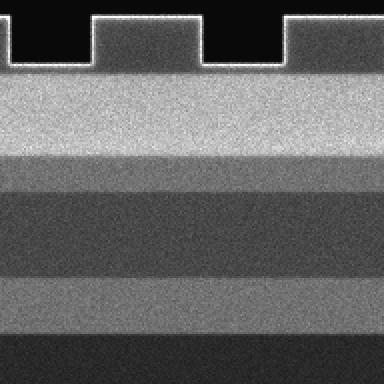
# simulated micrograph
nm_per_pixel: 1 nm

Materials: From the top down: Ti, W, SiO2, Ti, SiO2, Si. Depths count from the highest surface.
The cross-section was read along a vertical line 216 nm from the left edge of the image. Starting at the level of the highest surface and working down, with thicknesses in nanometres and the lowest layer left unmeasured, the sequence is empty 48, Ti 10, W 82, SiO2 36, Ti 86, SiO2 56, Si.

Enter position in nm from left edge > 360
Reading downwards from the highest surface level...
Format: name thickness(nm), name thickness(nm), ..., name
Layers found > Ti 58, W 82, SiO2 36, Ti 86, SiO2 56, Si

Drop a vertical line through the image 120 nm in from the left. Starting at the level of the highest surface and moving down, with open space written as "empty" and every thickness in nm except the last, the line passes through Ti 58, W 82, SiO2 36, Ti 86, SiO2 56, Si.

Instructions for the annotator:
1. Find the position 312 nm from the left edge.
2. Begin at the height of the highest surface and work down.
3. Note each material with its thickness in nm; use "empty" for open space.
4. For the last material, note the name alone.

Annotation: Ti 58, W 82, SiO2 36, Ti 86, SiO2 56, Si